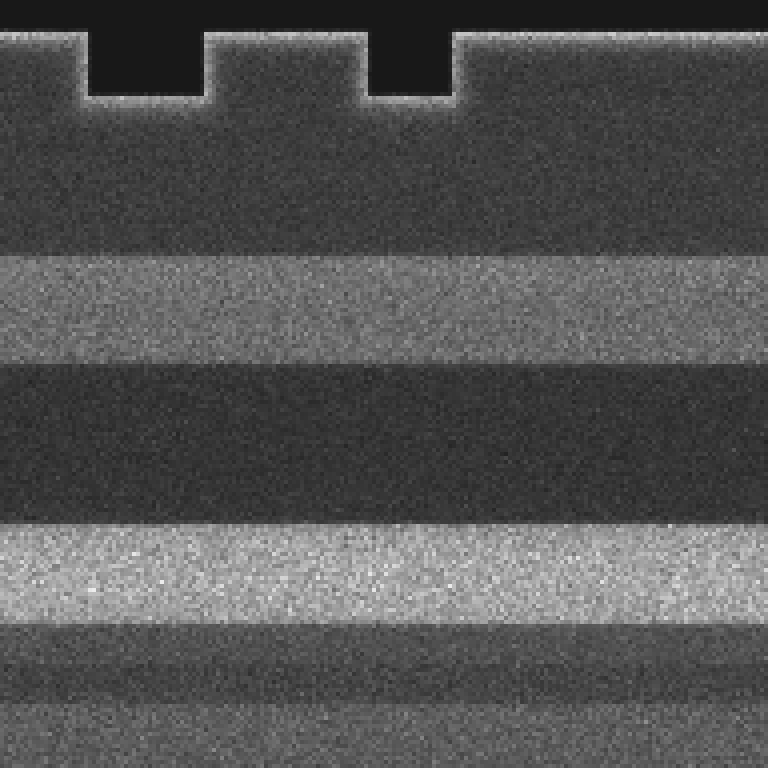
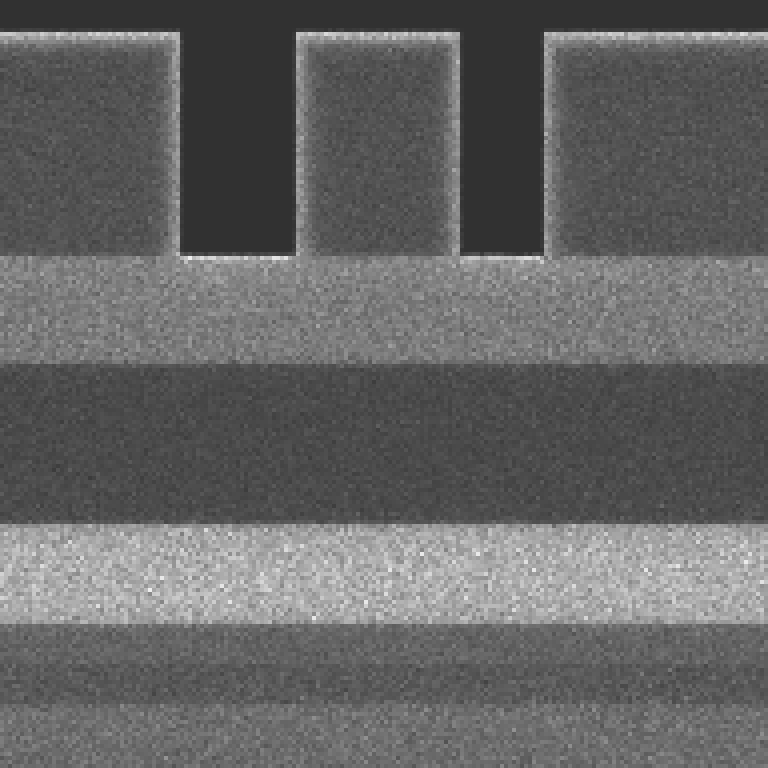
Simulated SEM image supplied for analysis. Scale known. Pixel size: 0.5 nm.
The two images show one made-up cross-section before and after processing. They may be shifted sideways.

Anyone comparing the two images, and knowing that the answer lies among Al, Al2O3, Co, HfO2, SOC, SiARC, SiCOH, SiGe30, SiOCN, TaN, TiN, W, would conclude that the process removed SOC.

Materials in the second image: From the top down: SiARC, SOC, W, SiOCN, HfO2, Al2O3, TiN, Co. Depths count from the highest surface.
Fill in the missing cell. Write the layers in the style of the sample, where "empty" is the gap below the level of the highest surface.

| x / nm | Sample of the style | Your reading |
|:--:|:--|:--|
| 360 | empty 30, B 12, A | SiARC 32, SOC 80, W 54, SiOCN 80, HfO2 50, Al2O3 20, TiN 20, Co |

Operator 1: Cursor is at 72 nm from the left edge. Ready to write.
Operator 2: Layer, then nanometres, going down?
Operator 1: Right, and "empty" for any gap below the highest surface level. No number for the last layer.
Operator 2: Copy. SiARC 32, SOC 80, W 54, SiOCN 80, HfO2 50, Al2O3 20, TiN 20, Co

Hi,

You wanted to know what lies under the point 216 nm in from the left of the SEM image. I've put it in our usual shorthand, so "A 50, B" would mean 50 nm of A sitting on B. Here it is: SiARC 32, SOC 80, W 54, SiOCN 80, HfO2 50, Al2O3 20, TiN 20, Co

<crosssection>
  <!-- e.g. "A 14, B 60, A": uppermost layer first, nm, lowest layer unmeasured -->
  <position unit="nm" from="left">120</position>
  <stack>empty 112, W 54, SiOCN 80, HfO2 50, Al2O3 20, TiN 20, Co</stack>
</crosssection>